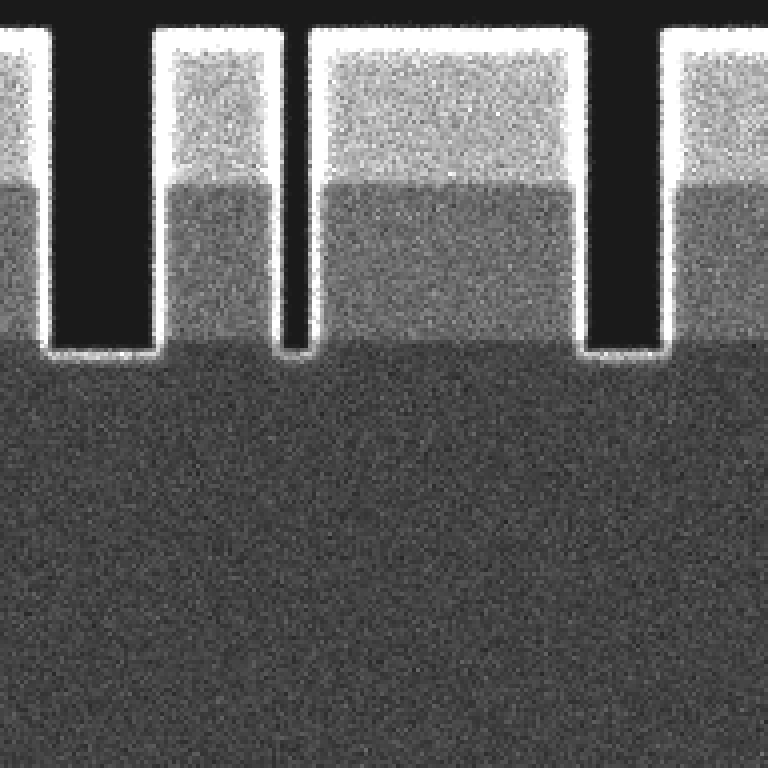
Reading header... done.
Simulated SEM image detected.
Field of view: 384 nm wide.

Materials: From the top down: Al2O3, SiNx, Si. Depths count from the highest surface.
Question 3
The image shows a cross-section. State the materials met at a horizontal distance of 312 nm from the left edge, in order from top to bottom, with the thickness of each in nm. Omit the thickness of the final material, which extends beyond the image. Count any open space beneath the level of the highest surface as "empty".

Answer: empty 160, Si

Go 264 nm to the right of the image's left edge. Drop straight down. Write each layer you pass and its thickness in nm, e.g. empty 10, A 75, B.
Al2O3 76, SiNx 78, Si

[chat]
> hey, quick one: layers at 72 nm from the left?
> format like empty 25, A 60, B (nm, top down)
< empty 160, Si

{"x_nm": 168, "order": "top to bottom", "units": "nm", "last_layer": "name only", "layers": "Al2O3 76, SiNx 78, Si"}